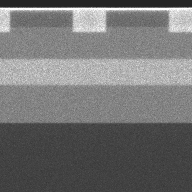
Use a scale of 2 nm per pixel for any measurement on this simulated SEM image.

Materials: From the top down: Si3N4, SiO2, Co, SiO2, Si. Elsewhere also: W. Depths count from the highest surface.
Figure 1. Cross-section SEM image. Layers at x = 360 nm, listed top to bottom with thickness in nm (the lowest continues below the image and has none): W 48, SiO2 54, Co 52, SiO2 76, Si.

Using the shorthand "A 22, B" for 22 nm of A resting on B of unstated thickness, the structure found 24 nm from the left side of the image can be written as Si3N4 38, SiO2 64, Co 52, SiO2 76, Si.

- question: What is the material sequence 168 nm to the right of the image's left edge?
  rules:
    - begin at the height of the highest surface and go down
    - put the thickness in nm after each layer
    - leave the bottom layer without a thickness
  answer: W 48, SiO2 54, Co 52, SiO2 76, Si